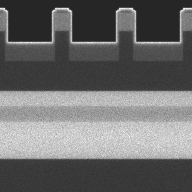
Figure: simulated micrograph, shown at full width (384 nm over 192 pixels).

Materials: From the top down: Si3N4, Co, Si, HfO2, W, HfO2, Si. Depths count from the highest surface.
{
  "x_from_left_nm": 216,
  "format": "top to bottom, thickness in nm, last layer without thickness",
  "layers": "empty 68, Si3N4 38, Si 60, HfO2 30, W 32, HfO2 74, Si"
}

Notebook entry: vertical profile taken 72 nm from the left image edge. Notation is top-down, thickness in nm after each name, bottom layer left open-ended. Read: empty 68, Si3N4 38, Si 60, HfO2 30, W 32, HfO2 74, Si